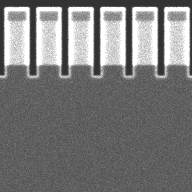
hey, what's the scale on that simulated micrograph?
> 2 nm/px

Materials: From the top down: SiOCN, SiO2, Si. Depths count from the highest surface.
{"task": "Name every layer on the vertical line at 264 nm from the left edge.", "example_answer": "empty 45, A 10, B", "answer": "empty 136, Si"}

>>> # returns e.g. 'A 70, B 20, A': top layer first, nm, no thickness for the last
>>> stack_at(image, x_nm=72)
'empty 136, Si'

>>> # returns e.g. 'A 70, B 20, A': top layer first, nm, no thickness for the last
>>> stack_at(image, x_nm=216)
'SiOCN 26, SiO2 88, Si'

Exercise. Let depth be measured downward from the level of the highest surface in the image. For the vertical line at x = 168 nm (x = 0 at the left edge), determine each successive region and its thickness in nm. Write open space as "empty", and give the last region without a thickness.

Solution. SiOCN 26, SiO2 88, Si